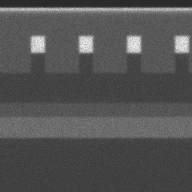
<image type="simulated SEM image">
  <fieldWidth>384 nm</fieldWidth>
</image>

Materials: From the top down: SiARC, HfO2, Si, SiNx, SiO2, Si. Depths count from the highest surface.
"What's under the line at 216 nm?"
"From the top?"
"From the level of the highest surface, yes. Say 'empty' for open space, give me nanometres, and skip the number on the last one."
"SiARC 130, Si 60, SiNx 28, SiO2 42, Si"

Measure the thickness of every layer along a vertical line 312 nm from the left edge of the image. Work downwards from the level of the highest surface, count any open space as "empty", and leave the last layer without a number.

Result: SiARC 130, Si 60, SiNx 28, SiO2 42, Si